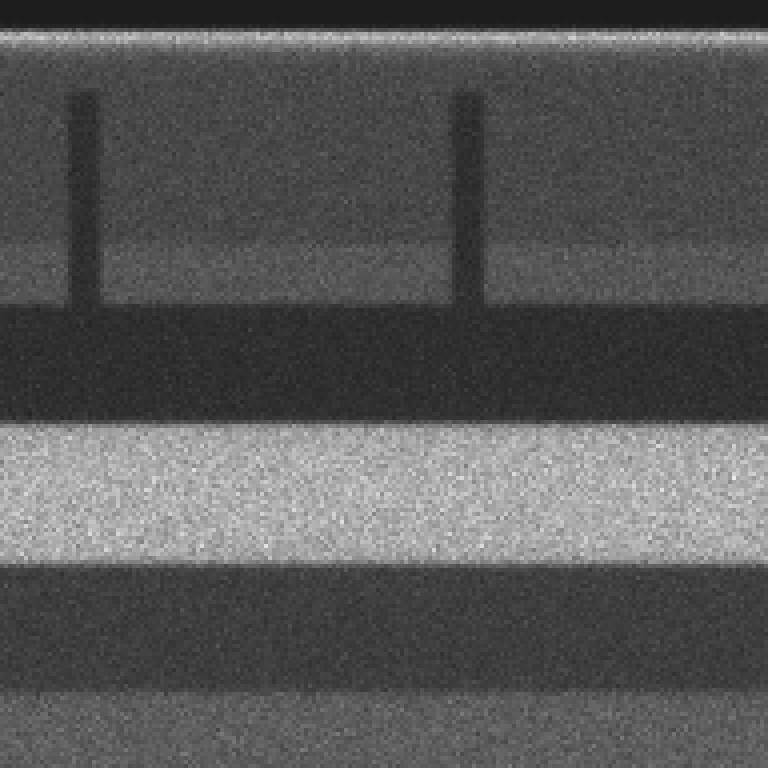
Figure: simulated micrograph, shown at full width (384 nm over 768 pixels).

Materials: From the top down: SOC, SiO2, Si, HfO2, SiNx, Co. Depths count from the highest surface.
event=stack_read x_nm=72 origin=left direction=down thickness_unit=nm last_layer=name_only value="SOC 106, SiO2 30, Si 60, HfO2 70, SiNx 64, Co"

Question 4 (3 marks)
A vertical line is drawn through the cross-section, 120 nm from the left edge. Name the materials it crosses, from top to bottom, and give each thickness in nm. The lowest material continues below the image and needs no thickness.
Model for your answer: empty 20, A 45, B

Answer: SOC 106, SiO2 30, Si 60, HfO2 70, SiNx 64, Co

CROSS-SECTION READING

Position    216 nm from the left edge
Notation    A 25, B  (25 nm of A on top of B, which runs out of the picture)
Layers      SOC 106, SiO2 30, Si 60, HfO2 70, SiNx 64, Co